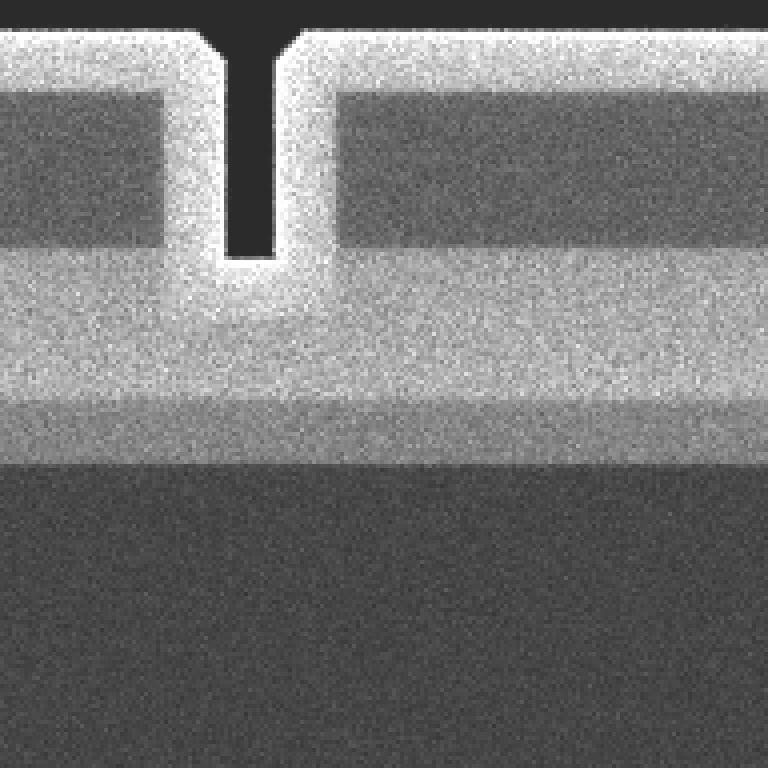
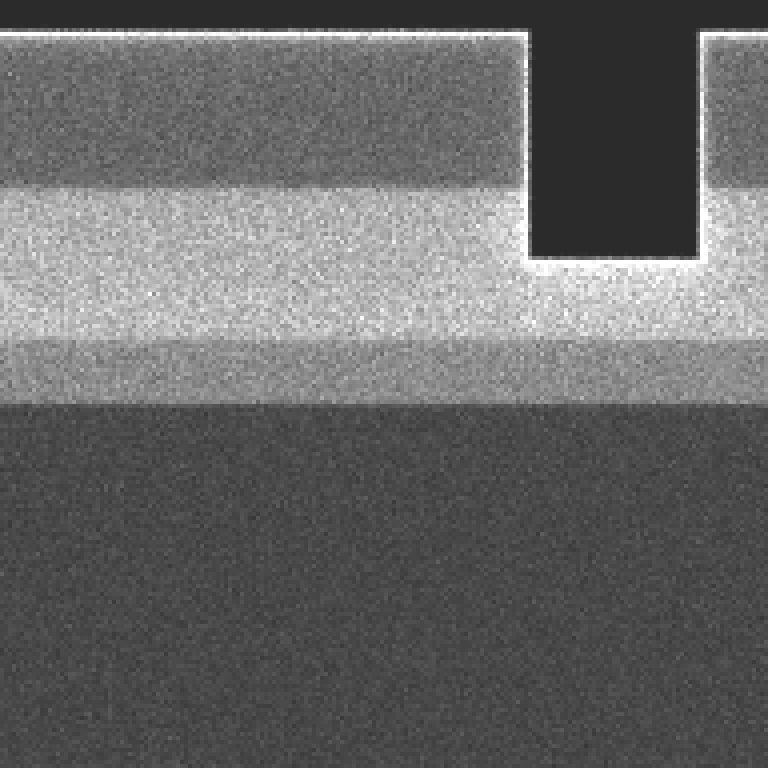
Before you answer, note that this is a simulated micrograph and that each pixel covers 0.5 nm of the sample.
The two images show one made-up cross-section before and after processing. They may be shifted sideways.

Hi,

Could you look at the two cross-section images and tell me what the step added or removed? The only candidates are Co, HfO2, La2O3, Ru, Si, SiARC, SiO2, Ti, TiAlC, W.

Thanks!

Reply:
removed W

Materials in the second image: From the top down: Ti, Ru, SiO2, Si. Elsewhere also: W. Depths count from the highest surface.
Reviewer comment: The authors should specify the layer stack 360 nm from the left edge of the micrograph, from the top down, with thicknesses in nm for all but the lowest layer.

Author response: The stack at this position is Ti 78, Ru 76, SiO2 32, Si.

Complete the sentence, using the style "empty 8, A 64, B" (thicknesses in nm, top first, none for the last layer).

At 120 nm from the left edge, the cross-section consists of Ti 78, Ru 76, SiO2 32, Si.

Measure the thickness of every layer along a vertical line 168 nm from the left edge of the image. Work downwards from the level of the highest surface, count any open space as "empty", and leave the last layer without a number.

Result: Ti 78, Ru 76, SiO2 32, Si